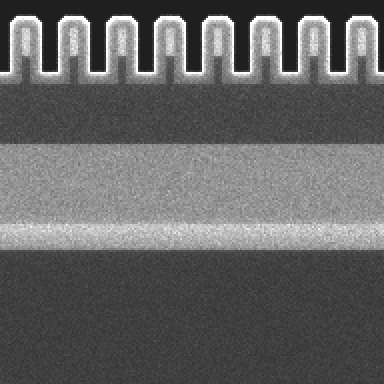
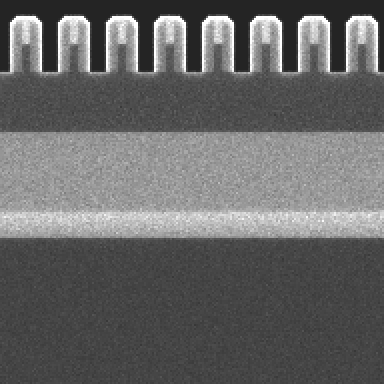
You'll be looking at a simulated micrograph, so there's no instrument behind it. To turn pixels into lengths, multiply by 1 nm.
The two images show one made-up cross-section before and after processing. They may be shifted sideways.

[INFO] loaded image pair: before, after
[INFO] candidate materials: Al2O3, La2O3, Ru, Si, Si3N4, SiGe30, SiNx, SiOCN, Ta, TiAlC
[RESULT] removed Si3N4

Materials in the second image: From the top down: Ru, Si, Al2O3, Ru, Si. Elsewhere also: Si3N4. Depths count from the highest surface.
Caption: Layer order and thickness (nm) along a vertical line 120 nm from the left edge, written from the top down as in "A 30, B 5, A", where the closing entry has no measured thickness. Ru 28, Si 88, Al2O3 80, Ru 26, Si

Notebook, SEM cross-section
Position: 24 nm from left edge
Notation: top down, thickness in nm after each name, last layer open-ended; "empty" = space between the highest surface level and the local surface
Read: Ru 28, Si 88, Al2O3 80, Ru 26, Si